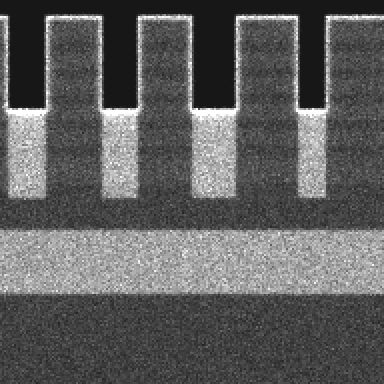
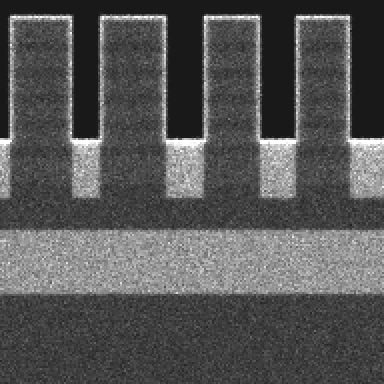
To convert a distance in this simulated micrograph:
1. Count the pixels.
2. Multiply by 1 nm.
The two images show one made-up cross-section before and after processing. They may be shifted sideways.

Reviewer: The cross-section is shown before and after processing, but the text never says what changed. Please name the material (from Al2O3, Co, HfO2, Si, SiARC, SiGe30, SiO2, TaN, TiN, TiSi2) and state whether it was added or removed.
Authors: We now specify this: Co, removed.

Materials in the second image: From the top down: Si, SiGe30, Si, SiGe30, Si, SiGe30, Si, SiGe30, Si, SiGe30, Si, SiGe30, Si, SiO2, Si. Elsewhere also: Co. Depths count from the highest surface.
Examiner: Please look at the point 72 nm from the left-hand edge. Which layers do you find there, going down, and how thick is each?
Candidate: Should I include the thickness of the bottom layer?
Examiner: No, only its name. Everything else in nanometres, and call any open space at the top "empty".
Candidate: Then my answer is empty 124, Co 58, Si 32, SiO2 64, Si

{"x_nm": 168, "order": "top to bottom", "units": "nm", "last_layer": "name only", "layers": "empty 124, Co 58, Si 32, SiO2 64, Si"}